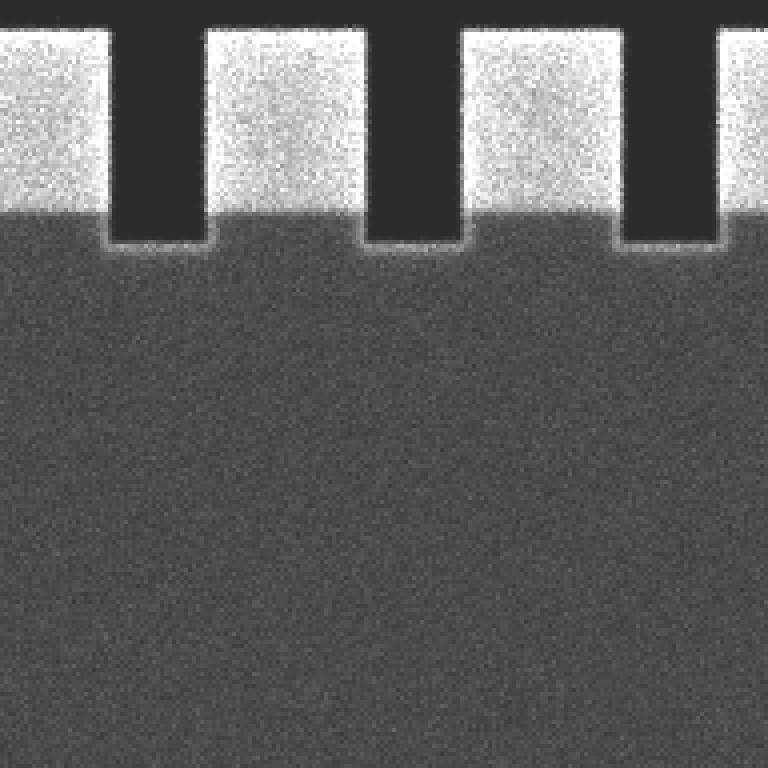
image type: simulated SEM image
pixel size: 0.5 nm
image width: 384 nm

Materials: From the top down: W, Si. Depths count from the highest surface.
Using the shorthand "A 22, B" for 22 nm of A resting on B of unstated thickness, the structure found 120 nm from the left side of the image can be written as W 90, Si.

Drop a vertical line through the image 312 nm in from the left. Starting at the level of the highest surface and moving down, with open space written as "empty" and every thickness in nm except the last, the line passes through empty 106, Si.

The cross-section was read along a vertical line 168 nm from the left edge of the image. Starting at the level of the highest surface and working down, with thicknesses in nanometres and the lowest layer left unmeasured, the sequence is W 90, Si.